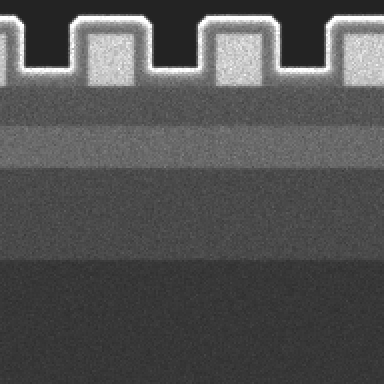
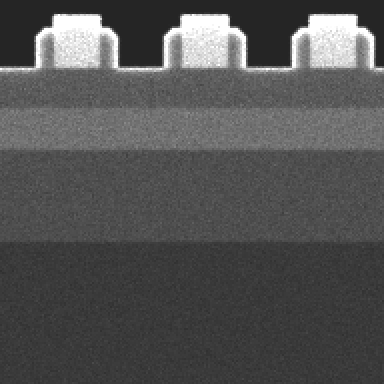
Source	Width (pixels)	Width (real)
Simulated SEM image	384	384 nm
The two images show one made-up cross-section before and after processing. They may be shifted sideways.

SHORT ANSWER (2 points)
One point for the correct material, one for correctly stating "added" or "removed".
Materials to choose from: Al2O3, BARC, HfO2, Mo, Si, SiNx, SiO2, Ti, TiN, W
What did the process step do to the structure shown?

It removed SiO2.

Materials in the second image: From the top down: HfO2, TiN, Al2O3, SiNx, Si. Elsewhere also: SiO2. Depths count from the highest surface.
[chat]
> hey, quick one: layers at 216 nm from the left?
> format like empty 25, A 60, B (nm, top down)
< HfO2 52, TiN 40, Al2O3 42, SiNx 92, Si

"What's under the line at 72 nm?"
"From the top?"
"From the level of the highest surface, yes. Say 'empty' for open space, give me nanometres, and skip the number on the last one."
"HfO2 52, TiN 40, Al2O3 42, SiNx 92, Si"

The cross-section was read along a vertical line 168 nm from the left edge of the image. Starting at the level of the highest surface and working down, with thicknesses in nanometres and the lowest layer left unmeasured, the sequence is empty 16, SiO2 36, TiN 40, Al2O3 42, SiNx 92, Si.